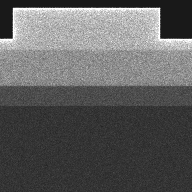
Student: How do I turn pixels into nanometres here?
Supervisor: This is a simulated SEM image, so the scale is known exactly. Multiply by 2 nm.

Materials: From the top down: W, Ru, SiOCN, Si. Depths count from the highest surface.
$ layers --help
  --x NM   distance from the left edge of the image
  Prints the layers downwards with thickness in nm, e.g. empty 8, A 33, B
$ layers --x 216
W 84, Ru 72, SiOCN 40, Si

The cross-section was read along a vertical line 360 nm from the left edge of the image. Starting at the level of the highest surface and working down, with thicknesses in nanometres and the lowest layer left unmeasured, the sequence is empty 62, W 22, Ru 72, SiOCN 40, Si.